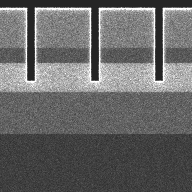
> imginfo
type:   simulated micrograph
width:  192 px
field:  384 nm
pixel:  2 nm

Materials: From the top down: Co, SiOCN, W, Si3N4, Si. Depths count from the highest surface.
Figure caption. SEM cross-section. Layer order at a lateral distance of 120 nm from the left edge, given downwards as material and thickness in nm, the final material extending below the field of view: Co 80, SiOCN 30, W 58, Si3N4 84, Si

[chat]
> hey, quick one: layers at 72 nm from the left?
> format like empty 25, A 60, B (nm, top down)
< Co 80, SiOCN 30, W 58, Si3N4 84, Si